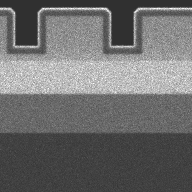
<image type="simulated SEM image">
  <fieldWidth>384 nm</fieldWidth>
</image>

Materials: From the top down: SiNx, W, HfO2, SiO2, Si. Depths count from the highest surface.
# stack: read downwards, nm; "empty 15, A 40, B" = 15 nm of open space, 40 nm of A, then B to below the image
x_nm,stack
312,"SiNx 16, W 90, HfO2 66, SiO2 78, Si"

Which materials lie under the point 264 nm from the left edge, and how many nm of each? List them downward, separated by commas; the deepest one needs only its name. empty 76, SiNx 16, W 14, HfO2 66, SiO2 78, Si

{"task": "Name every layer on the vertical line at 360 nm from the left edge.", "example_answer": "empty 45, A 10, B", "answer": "SiNx 16, W 90, HfO2 66, SiO2 78, Si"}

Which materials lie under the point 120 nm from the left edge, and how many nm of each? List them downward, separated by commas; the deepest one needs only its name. SiNx 16, W 90, HfO2 66, SiO2 78, Si